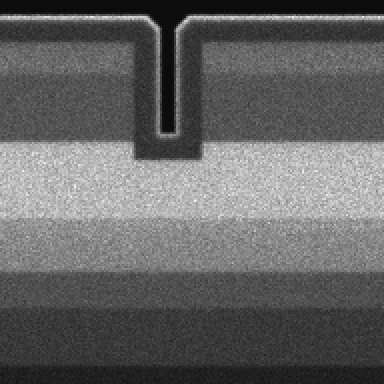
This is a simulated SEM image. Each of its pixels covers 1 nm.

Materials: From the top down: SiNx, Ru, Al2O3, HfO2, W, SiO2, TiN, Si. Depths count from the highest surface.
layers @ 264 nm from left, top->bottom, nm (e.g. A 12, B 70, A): SiNx 26, Ru 32, Al2O3 68, HfO2 76, W 54, SiO2 36, TiN 58, Si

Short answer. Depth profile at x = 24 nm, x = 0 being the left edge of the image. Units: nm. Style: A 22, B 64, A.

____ SiNx 26, Ru 32, Al2O3 68, HfO2 76, W 54, SiO2 36, TiN 58, Si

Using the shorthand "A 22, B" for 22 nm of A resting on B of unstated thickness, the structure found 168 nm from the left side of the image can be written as empty 118, SiNx 26, HfO2 58, W 54, SiO2 36, TiN 58, Si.